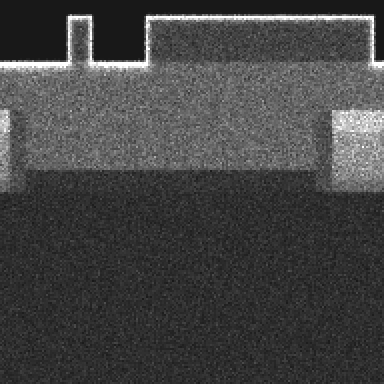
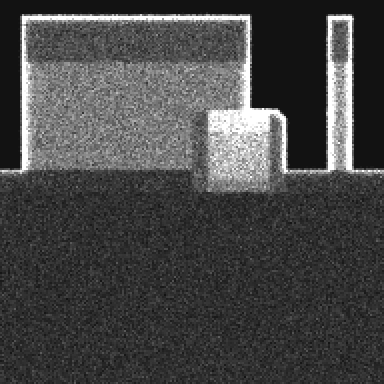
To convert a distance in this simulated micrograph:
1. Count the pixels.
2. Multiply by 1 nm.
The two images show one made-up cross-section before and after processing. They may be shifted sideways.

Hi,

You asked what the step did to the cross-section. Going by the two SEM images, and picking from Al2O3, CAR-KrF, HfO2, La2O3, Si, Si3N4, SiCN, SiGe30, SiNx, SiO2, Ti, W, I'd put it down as SiO2, removed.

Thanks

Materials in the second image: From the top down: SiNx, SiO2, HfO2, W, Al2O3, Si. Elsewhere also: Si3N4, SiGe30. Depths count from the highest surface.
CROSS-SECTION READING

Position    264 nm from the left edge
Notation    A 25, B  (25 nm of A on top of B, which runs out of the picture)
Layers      empty 94, HfO2 22, W 48, Al2O3 12, Si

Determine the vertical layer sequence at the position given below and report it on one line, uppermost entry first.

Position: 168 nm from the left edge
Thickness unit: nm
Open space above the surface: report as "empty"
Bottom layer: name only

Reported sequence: SiNx 46, SiO2 108, SiGe30 22, Si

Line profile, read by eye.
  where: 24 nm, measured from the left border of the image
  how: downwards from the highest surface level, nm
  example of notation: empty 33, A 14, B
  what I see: SiNx 46, SiO2 108, SiGe30 22, Si